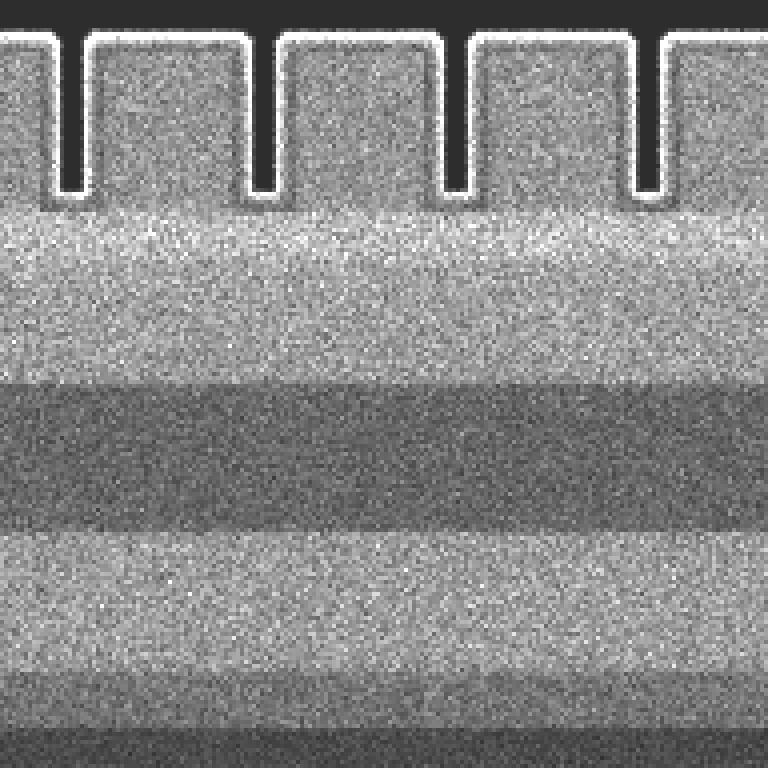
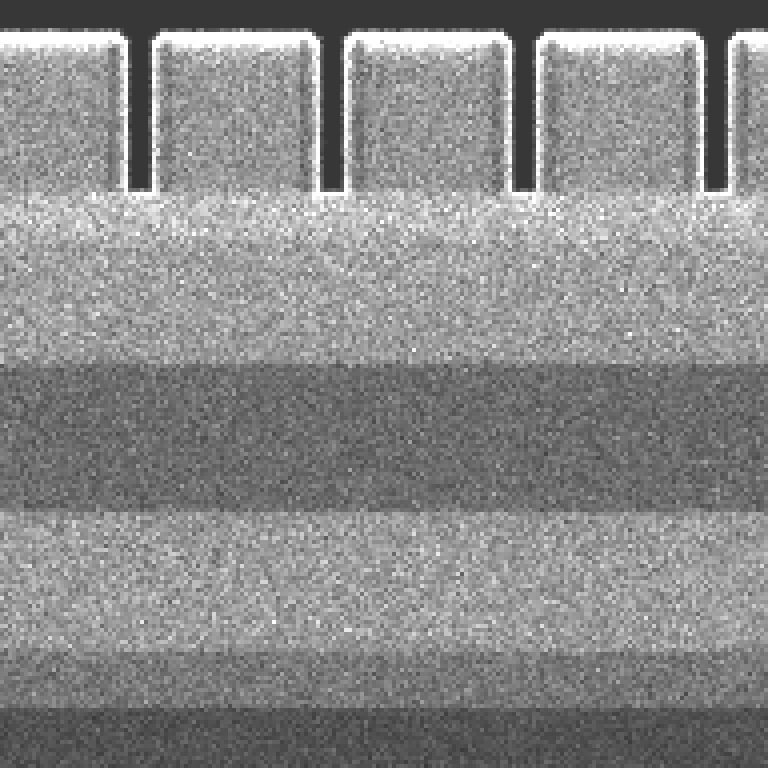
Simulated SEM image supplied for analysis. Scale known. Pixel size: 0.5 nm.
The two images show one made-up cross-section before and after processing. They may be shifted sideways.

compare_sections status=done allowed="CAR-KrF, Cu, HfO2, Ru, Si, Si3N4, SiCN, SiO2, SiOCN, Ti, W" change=removed material="SiOCN"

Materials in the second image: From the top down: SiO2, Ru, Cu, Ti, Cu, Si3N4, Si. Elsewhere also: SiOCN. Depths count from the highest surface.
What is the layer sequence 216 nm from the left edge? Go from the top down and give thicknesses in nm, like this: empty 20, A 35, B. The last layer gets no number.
SiO2 80, Ru 24, Cu 62, Ti 74, Cu 70, Si3N4 28, Si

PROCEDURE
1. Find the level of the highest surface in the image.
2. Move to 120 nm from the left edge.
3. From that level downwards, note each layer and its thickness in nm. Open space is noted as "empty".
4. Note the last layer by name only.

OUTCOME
SiO2 80, Ru 24, Cu 62, Ti 74, Cu 70, Si3N4 28, Si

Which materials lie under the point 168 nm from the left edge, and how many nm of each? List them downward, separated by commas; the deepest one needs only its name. empty 80, Ru 24, Cu 62, Ti 74, Cu 70, Si3N4 28, Si